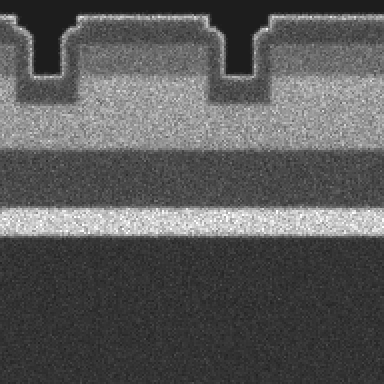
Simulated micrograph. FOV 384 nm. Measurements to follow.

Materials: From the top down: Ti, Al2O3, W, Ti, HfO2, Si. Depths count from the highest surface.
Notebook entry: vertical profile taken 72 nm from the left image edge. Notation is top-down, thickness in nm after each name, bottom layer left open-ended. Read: empty 12, Ti 76, W 46, Ti 58, HfO2 28, Si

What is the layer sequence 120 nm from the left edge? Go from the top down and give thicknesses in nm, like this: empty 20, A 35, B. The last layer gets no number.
Ti 28, Al2O3 32, W 74, Ti 58, HfO2 28, Si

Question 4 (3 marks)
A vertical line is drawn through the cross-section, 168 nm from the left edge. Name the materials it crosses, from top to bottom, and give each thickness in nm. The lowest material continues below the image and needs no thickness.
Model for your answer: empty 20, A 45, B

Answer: Ti 28, Al2O3 32, W 74, Ti 58, HfO2 28, Si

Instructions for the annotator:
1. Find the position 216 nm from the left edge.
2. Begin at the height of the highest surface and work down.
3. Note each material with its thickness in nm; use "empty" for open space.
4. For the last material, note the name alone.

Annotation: empty 14, Ti 74, W 46, Ti 58, HfO2 28, Si